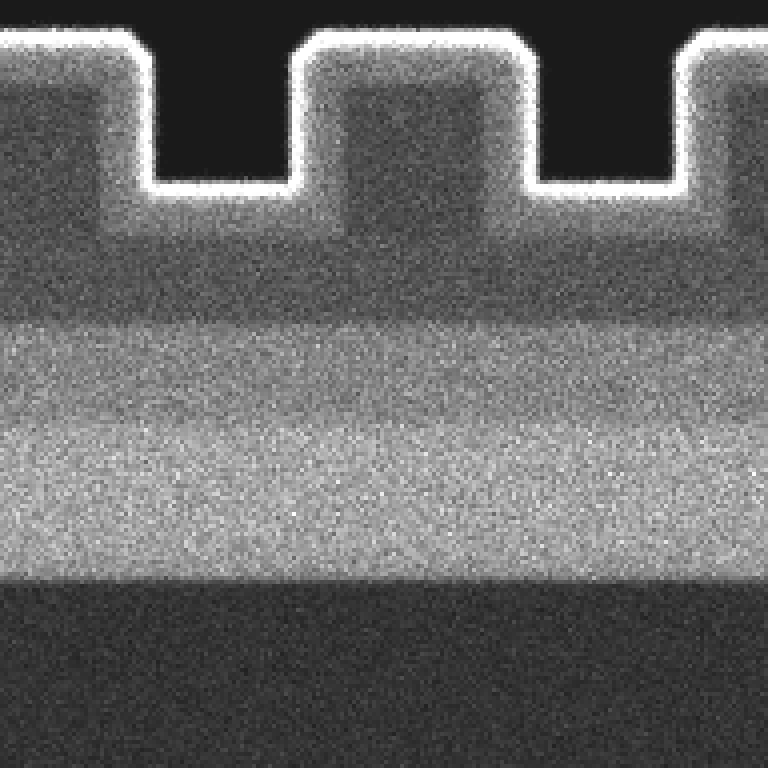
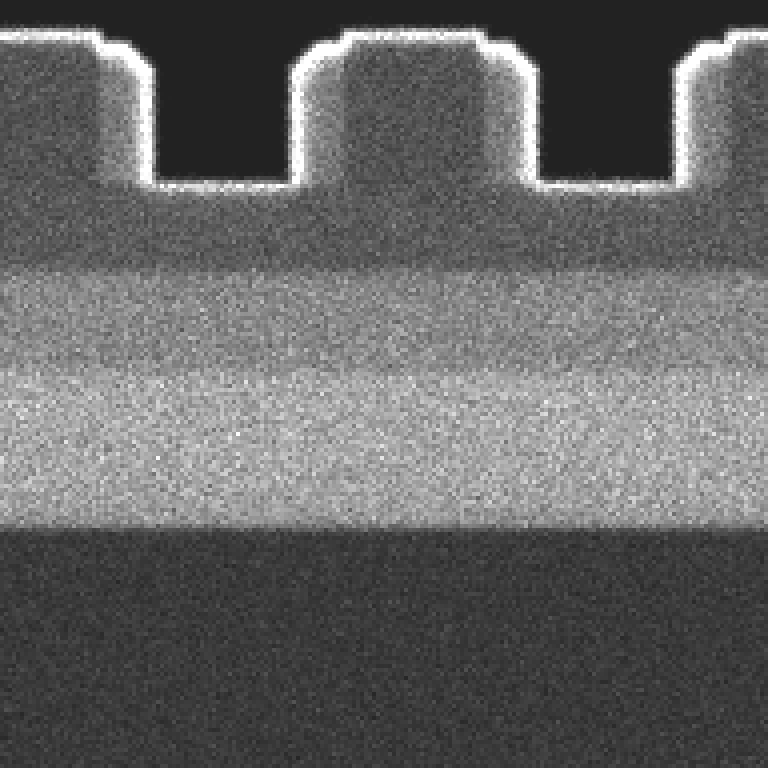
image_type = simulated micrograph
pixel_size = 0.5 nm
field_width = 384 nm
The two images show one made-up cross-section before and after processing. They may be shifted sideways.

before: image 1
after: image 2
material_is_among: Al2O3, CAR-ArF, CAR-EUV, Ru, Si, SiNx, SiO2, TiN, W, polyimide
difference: SiO2, removed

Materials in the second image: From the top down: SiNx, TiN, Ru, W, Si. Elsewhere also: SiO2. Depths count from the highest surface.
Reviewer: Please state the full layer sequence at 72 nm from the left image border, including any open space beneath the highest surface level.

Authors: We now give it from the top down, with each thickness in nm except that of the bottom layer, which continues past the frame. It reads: empty 16, SiO2 60, TiN 44, Ru 50, W 78, Si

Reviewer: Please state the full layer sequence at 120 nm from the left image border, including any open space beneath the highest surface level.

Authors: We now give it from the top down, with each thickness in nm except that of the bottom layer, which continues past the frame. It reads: empty 76, TiN 44, Ru 50, W 78, Si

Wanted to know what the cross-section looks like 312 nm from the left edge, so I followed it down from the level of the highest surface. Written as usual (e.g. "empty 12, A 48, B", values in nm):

empty 76, TiN 44, Ru 50, W 78, Si